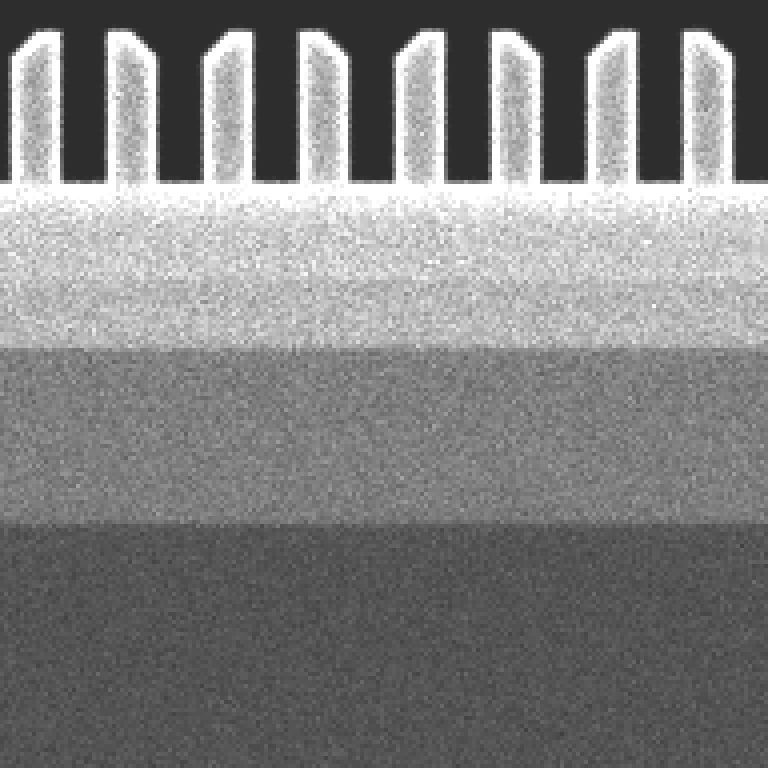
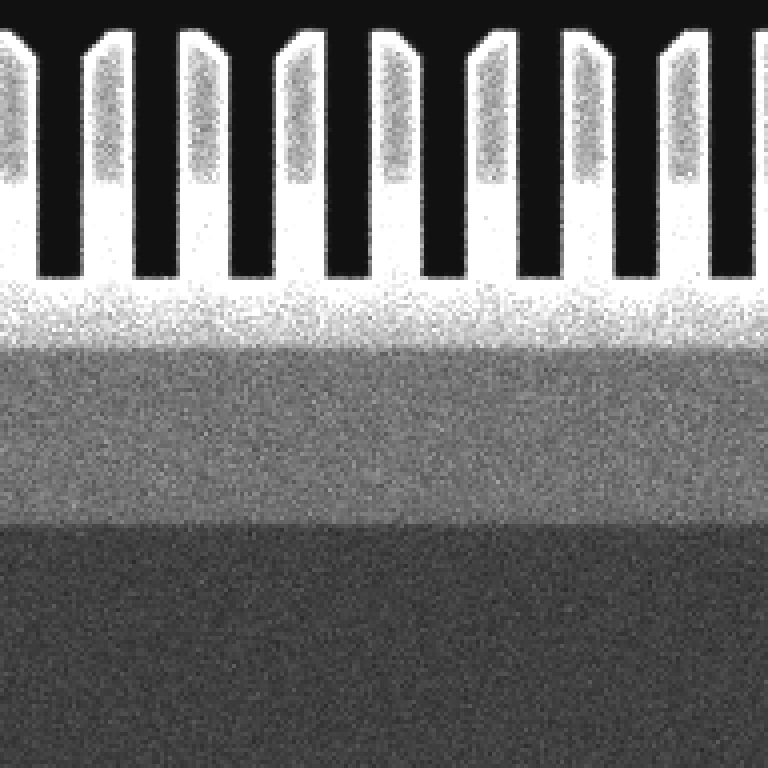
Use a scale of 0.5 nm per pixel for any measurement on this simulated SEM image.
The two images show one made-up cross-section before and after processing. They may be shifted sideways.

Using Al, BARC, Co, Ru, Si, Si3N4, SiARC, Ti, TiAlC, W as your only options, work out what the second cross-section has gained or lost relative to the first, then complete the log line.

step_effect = removed W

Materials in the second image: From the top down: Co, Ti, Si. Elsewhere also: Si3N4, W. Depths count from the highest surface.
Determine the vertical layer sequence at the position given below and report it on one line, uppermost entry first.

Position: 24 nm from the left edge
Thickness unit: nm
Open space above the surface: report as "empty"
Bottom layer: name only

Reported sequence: empty 124, Co 34, Ti 88, Si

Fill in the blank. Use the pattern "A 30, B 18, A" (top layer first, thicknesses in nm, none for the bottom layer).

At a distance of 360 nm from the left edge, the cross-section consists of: empty 124, Co 34, Ti 88, Si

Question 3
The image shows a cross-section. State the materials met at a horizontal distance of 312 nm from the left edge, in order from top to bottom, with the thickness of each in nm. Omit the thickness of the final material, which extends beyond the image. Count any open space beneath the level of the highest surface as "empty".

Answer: empty 124, Co 34, Ti 88, Si